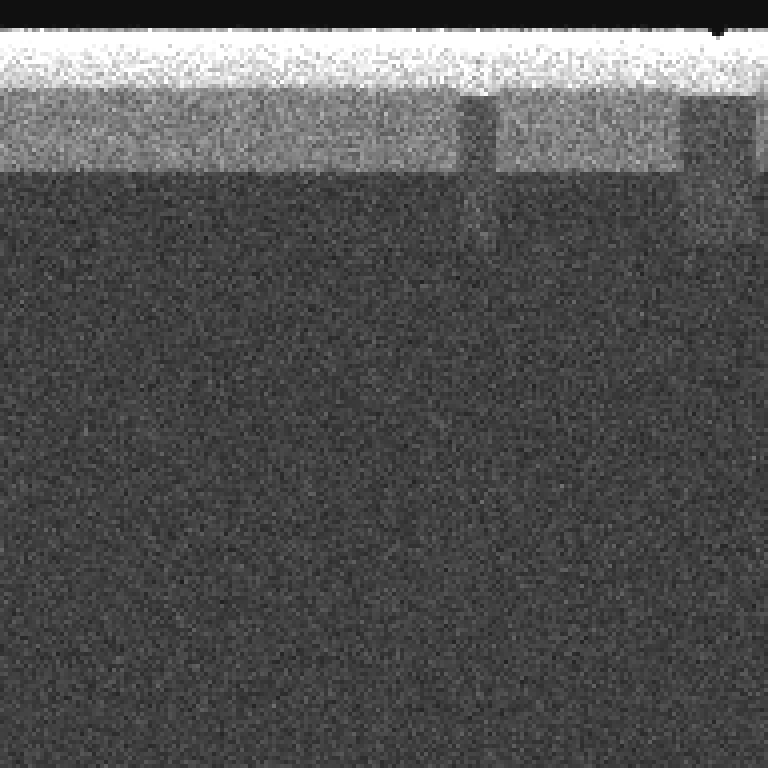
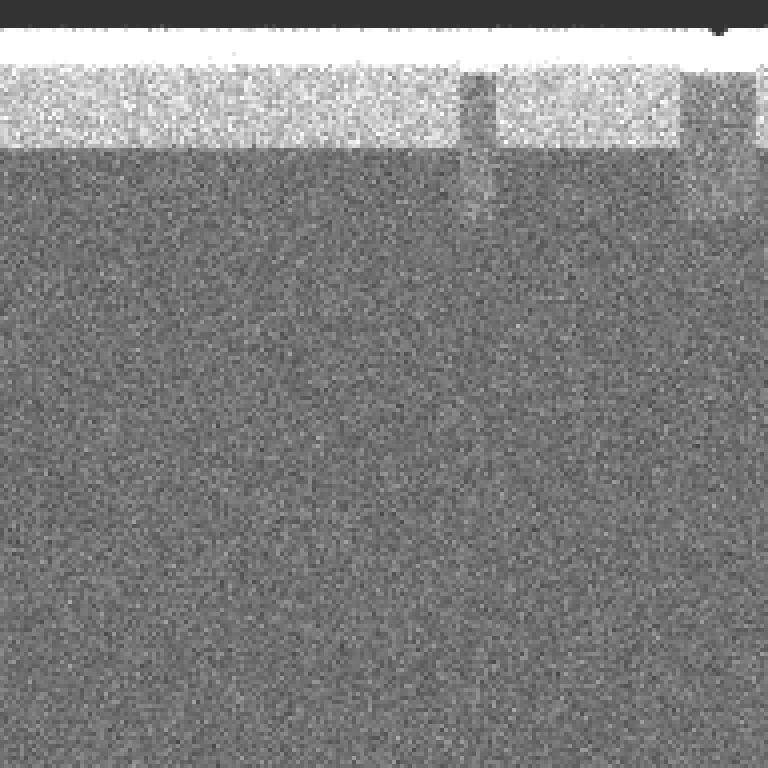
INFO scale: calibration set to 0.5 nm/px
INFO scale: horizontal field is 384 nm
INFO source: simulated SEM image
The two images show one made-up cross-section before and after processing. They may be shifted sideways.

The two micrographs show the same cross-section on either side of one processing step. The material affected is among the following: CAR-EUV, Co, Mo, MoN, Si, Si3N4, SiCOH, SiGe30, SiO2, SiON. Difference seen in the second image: Co removed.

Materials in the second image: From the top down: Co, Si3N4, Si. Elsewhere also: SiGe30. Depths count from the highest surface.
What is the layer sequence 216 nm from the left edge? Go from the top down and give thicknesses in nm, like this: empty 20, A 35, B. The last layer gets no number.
Co 16, Si3N4 42, Si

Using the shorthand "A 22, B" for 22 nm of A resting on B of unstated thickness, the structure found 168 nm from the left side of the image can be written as Co 16, Si3N4 42, Si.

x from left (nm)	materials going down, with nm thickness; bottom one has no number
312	Co 16, Si3N4 42, Si